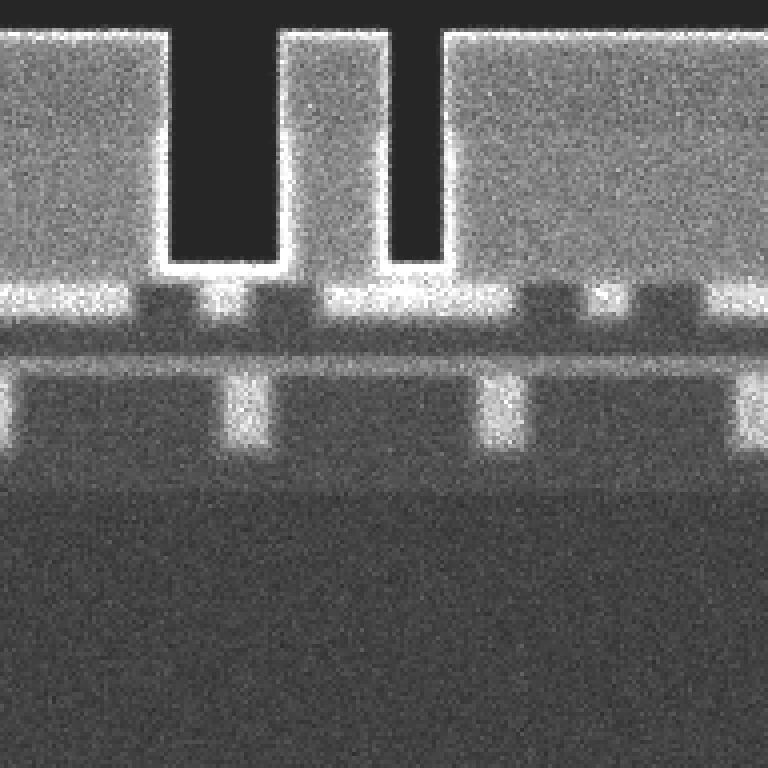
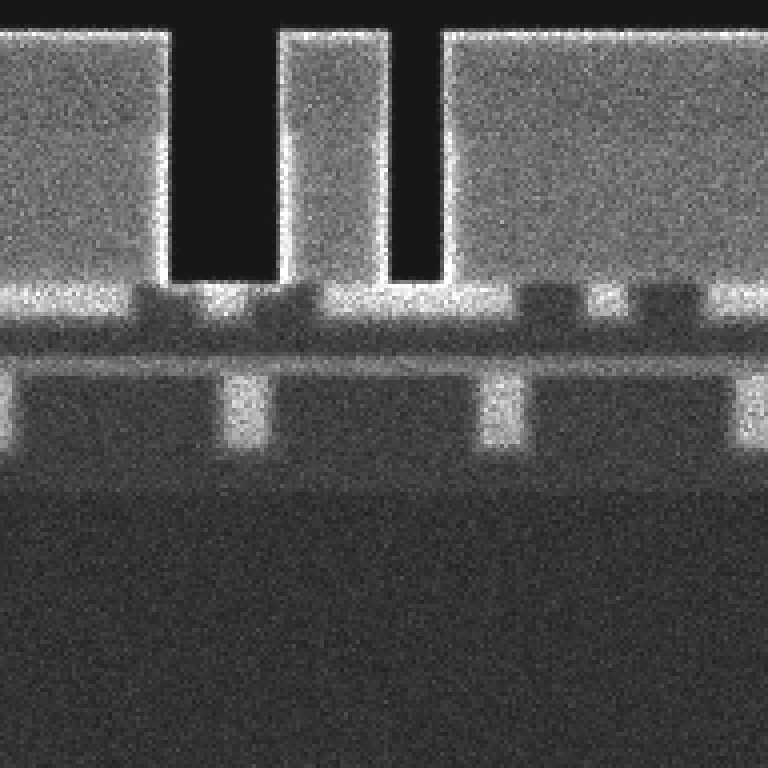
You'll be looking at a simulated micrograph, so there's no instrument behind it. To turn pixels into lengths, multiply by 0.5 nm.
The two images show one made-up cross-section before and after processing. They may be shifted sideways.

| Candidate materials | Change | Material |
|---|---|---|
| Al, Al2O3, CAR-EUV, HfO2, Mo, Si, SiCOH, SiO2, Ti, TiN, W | removed | Al2O3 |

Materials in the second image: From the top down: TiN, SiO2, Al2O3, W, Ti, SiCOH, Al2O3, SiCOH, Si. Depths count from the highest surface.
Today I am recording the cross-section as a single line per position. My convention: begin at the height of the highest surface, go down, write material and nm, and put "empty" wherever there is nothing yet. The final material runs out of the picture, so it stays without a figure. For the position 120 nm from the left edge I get empty 126, W 16, Ti 6, SiCOH 14, Al2O3 10, W 36, Ti 6, SiCOH 16, Si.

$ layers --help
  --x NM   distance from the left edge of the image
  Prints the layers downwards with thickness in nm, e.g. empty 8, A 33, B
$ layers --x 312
TiN 50, SiO2 66, Al2O3 10, W 16, Ti 6, SiCOH 14, Al2O3 10, SiCOH 58, Si